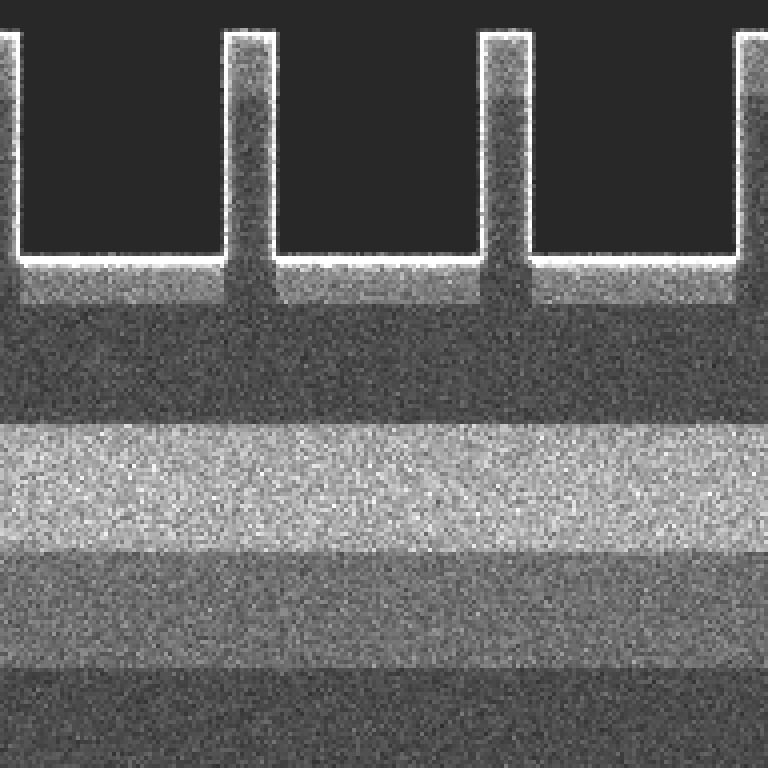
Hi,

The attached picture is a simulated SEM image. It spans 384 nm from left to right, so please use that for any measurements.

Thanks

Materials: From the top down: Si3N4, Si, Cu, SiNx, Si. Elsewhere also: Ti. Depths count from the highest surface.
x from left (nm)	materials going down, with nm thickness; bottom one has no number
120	Ti 32, Si 164, Cu 64, SiNx 58, Si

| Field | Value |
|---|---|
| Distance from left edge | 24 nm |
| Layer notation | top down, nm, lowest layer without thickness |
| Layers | empty 112, Si3N4 24, Si 60, Cu 64, SiNx 58, Si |